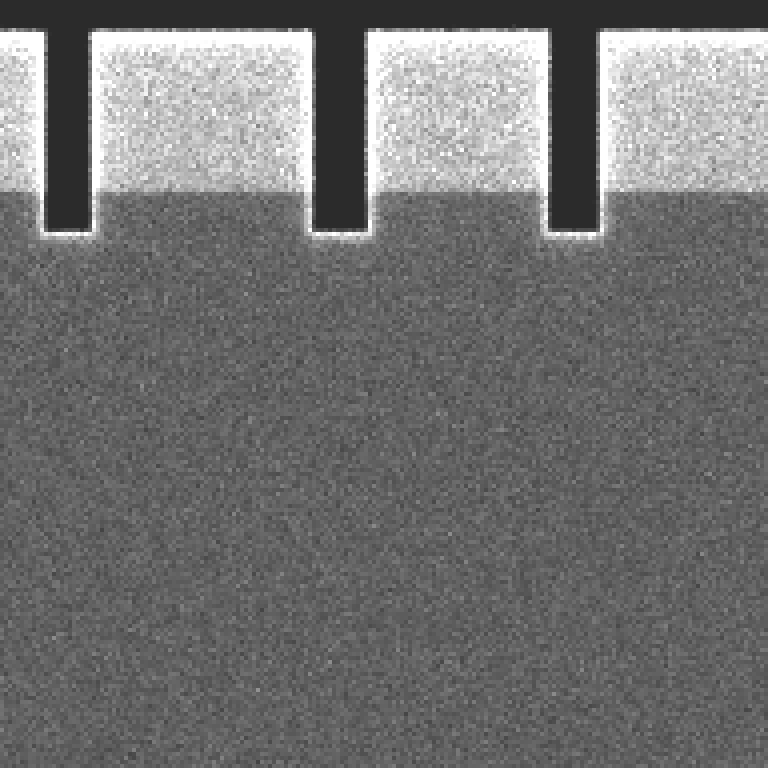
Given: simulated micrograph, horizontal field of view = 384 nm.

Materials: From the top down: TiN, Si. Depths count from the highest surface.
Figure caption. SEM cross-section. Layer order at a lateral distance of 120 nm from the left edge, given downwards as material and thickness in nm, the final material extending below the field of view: TiN 80, Si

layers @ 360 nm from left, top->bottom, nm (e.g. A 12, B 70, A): TiN 80, Si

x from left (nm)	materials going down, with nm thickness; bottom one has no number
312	TiN 80, Si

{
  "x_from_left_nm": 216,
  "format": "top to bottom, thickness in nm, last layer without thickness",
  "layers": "TiN 80, Si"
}